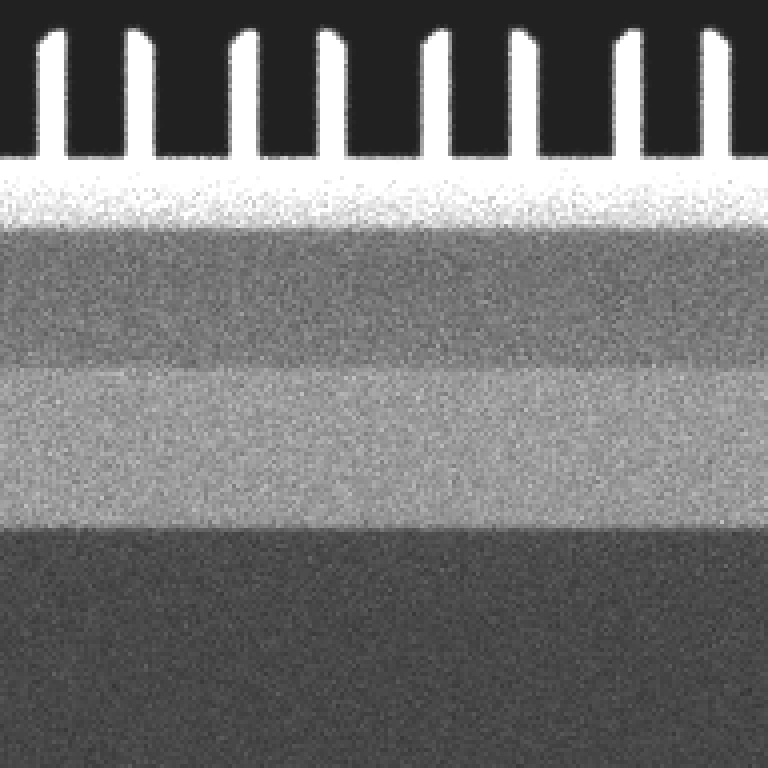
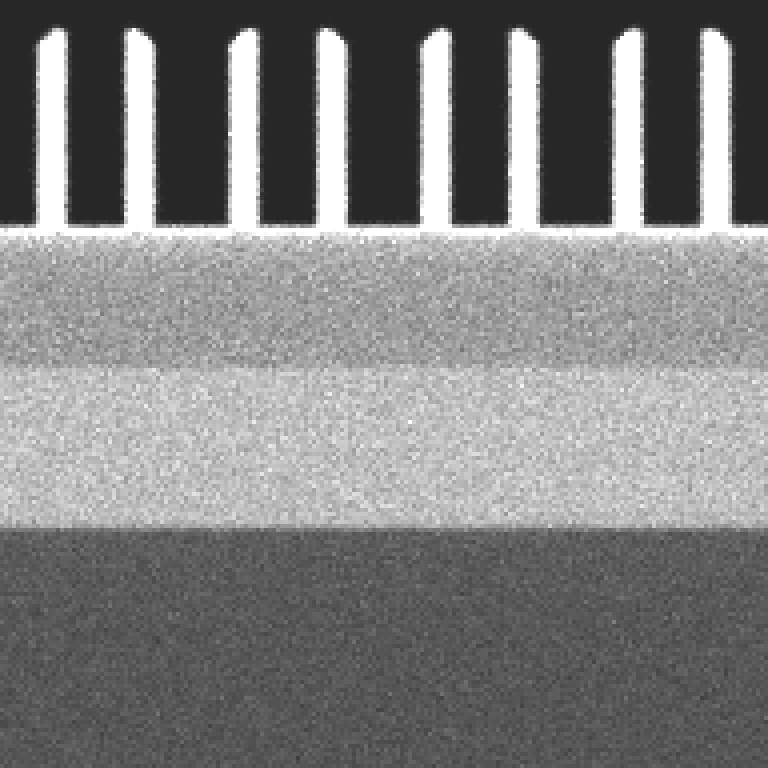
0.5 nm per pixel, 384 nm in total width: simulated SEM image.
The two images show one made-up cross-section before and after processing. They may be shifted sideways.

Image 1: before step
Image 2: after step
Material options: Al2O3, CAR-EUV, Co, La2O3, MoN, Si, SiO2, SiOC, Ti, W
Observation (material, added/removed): W, removed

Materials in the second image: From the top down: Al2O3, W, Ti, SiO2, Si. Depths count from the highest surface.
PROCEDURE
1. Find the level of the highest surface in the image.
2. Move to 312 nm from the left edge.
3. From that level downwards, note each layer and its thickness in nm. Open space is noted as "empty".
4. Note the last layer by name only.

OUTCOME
empty 2, Al2O3 62, W 34, Ti 70, SiO2 80, Si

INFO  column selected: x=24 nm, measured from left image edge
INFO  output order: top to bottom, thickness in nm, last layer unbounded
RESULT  empty 2, Al2O3 62, W 34, Ti 70, SiO2 80, Si